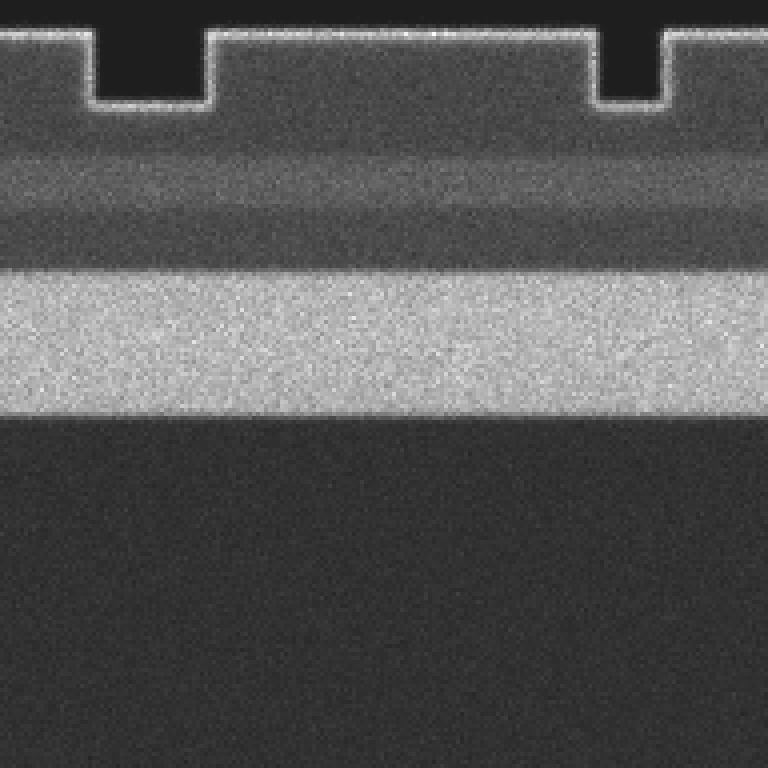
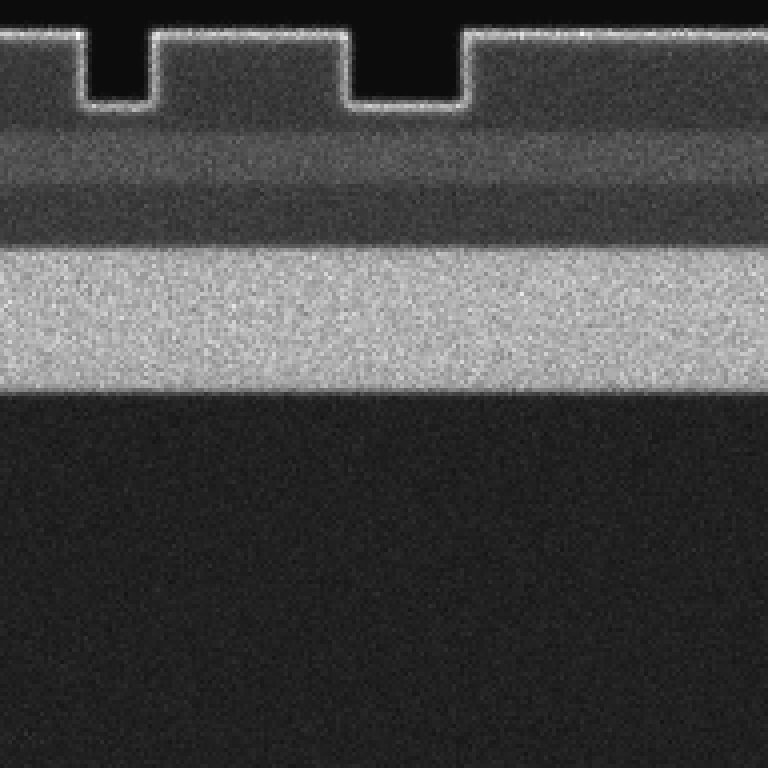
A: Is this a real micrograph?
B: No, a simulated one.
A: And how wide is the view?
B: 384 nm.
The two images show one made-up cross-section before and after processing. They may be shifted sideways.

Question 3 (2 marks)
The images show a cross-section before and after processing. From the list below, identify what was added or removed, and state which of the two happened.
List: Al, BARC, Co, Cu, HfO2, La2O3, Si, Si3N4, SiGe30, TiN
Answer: TiN was removed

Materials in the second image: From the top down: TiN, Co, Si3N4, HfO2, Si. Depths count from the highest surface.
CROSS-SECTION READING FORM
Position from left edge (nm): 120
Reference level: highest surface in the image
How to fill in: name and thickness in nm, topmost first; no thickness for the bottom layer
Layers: TiN 50, Co 26, Si3N4 32, HfO2 72, Si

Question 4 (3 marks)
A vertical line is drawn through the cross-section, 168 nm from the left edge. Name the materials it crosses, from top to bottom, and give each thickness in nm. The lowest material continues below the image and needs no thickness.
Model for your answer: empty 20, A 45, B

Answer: TiN 50, Co 26, Si3N4 32, HfO2 72, Si